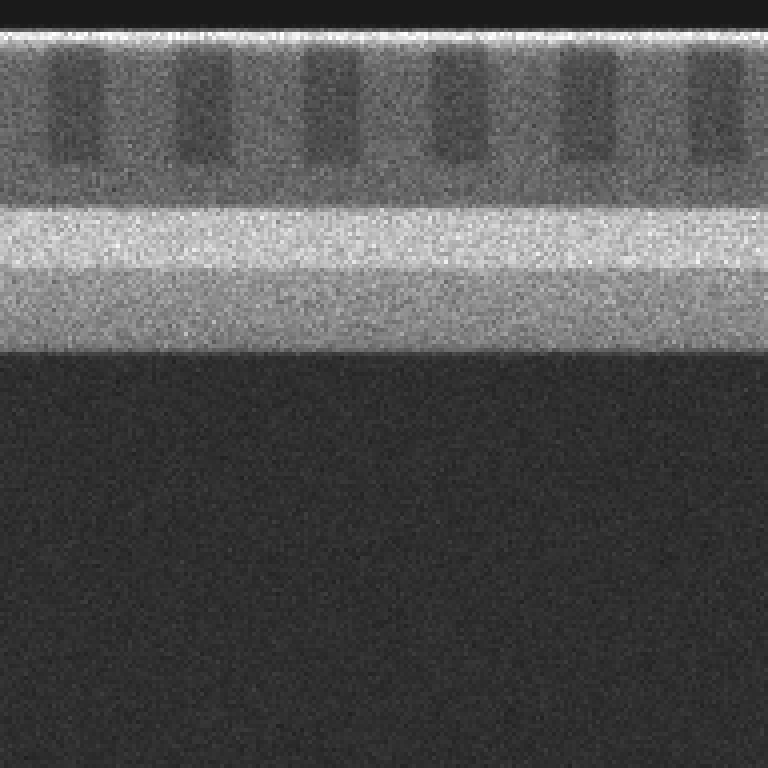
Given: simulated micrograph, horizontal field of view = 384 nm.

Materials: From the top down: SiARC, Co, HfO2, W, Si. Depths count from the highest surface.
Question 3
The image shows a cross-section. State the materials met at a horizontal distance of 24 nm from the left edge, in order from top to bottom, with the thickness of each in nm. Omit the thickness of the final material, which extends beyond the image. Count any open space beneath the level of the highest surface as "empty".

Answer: SiARC 66, Co 22, HfO2 30, W 42, Si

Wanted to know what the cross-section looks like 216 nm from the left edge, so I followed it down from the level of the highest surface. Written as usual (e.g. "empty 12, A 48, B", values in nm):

SiARC 66, Co 22, HfO2 30, W 42, Si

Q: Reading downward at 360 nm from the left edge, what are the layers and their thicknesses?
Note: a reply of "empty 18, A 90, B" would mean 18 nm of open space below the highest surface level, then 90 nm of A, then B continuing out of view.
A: SiARC 66, Co 22, HfO2 30, W 42, Si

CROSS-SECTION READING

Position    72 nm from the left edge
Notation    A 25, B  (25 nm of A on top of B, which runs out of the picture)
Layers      SiARC 6, Co 82, HfO2 30, W 42, Si